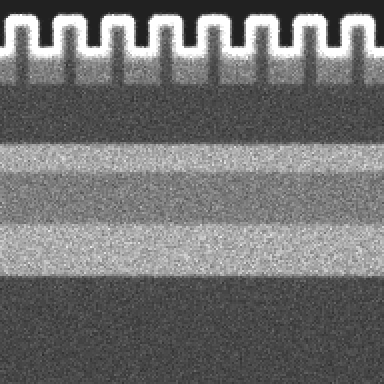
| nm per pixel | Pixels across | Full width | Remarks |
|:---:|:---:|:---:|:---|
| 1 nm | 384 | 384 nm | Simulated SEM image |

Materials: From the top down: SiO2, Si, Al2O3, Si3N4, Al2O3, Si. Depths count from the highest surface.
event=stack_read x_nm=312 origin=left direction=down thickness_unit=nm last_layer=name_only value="SiO2 10, Si 118, Al2O3 28, Si3N4 52, Al2O3 52, Si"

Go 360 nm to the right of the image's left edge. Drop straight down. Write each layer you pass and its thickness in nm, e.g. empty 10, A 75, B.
SiO2 10, Si 118, Al2O3 28, Si3N4 52, Al2O3 52, Si